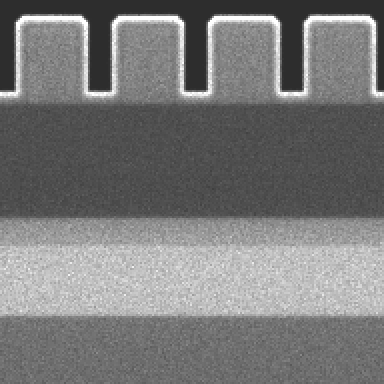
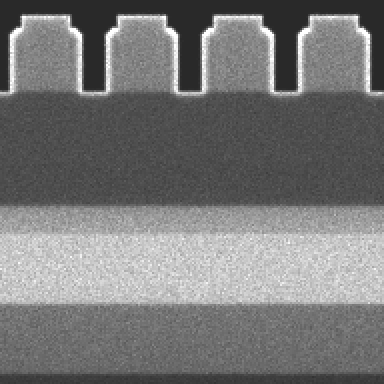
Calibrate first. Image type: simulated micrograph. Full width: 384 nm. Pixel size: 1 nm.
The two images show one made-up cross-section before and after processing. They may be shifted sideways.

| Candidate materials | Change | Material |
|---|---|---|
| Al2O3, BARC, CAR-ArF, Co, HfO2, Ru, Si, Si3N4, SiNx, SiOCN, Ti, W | removed | Al2O3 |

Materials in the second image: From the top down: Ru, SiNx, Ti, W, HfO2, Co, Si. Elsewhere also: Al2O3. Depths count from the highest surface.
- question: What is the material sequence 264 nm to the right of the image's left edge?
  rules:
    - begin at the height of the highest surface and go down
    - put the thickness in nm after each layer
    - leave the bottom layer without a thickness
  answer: empty 12, Al2O3 64, SiNx 72, Ti 42, W 28, HfO2 70, Co 70, Si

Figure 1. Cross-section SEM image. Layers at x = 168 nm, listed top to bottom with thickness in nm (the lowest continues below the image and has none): empty 12, Al2O3 64, SiNx 72, Ti 42, W 28, HfO2 70, Co 70, Si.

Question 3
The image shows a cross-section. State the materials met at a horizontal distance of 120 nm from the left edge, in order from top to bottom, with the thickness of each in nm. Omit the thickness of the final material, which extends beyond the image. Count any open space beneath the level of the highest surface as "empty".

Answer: Ru 76, SiNx 72, Ti 42, W 28, HfO2 70, Co 70, Si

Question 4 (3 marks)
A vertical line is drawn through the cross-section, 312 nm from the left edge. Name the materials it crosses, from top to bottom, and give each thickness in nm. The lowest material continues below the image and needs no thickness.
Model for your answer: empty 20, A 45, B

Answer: Ru 76, SiNx 72, Ti 42, W 28, HfO2 70, Co 70, Si